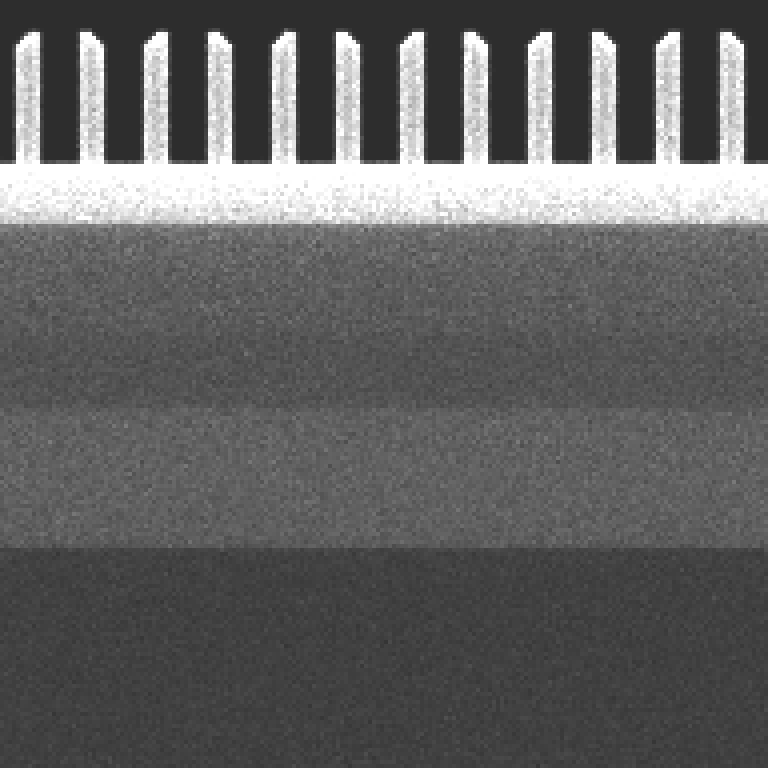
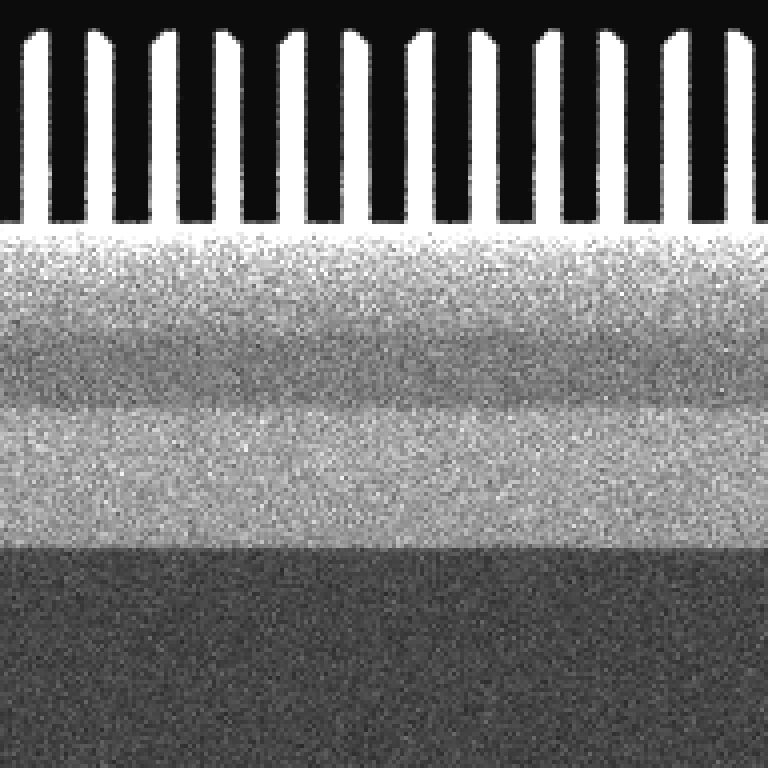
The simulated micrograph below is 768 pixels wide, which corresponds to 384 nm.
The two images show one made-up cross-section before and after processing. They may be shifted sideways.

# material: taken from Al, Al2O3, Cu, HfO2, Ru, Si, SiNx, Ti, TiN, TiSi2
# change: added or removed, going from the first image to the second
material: HfO2
change: removed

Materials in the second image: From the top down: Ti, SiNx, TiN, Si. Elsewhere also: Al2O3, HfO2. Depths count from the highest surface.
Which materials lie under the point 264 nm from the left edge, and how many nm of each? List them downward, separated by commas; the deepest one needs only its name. empty 96, Ti 54, SiNx 38, TiN 70, Si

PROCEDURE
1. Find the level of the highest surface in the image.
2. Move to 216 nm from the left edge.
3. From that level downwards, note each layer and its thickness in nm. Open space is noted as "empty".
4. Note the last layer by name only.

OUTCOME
empty 96, Ti 54, SiNx 38, TiN 70, Si